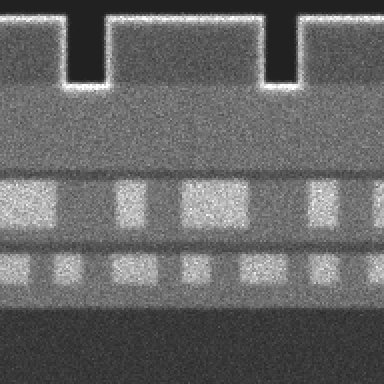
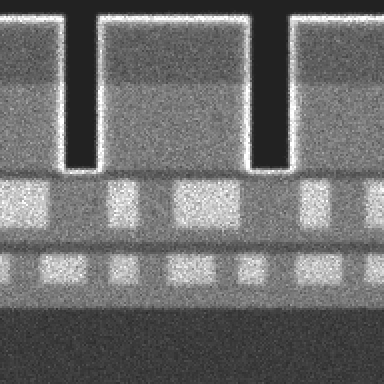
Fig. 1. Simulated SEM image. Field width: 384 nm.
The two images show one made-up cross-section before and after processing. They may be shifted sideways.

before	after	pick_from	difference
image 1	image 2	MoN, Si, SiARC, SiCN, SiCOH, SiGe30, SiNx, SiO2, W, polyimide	SiO2 removed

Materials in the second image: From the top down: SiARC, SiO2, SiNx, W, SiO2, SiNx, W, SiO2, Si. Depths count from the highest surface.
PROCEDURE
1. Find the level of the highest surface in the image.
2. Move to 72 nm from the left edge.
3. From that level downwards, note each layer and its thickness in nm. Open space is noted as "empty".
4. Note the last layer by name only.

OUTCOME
empty 154, SiNx 10, SiO2 62, SiNx 12, W 30, SiO2 24, Si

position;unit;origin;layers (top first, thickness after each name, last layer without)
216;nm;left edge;SiARC 68, SiO2 86, SiNx 10, W 48, SiO2 14, SiNx 12, SiO2 54, Si